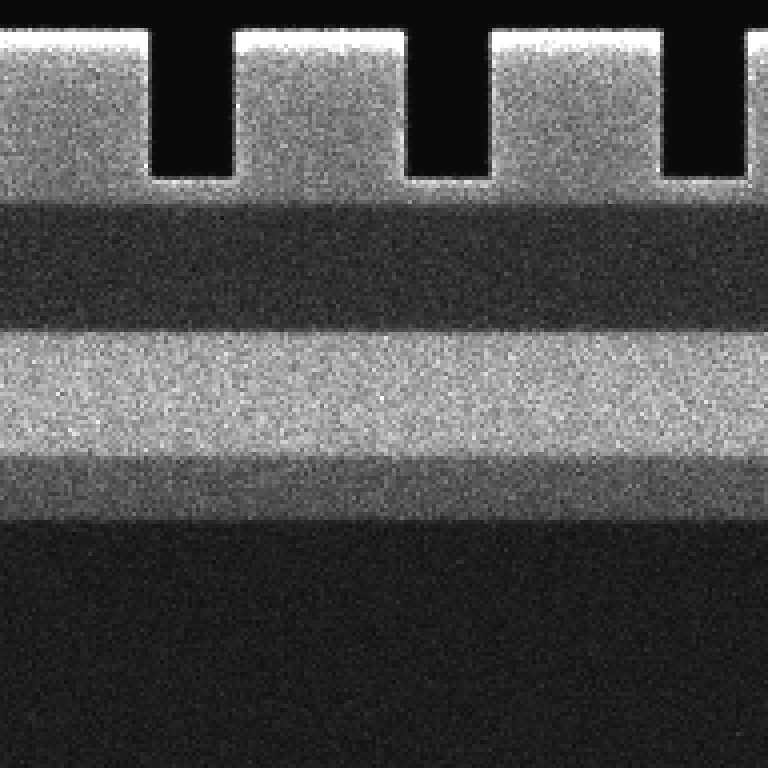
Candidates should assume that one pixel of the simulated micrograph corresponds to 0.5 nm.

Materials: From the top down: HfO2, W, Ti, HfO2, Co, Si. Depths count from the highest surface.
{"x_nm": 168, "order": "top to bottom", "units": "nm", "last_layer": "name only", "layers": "HfO2 10, W 76, Ti 64, HfO2 62, Co 32, Si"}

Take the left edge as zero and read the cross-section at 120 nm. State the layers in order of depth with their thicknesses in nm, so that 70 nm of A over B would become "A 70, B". HfO2 10, W 76, Ti 64, HfO2 62, Co 32, Si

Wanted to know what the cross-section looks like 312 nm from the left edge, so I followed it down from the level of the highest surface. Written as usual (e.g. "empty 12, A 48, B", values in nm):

HfO2 10, W 76, Ti 64, HfO2 62, Co 32, Si